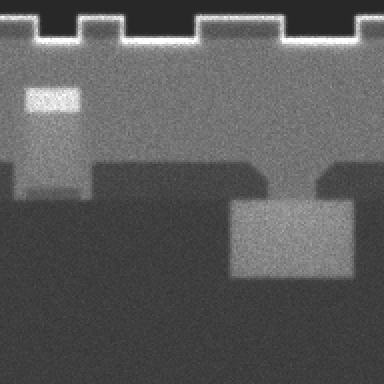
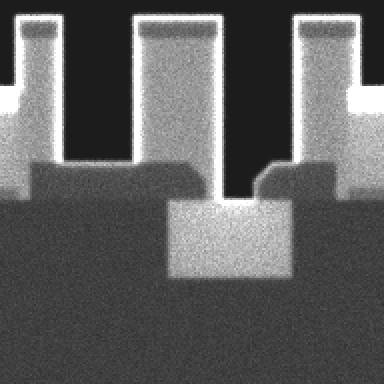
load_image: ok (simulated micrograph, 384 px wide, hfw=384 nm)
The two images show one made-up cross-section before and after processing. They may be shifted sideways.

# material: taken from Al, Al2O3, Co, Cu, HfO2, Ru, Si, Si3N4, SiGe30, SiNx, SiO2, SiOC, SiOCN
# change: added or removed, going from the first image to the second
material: SiO2
change: removed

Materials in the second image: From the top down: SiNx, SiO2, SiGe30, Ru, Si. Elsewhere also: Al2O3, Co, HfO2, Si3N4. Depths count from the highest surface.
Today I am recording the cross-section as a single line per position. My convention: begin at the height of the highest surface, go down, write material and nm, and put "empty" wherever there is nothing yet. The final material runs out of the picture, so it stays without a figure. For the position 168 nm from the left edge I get SiNx 22, SiO2 124, SiGe30 38, Ru 78, Si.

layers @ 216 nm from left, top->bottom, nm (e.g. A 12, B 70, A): SiNx 22, SiO2 162, Ru 78, Si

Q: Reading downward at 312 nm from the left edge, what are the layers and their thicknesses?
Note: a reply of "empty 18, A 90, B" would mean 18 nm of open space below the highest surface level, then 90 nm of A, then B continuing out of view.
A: SiNx 22, SiO2 124, SiGe30 38, Si